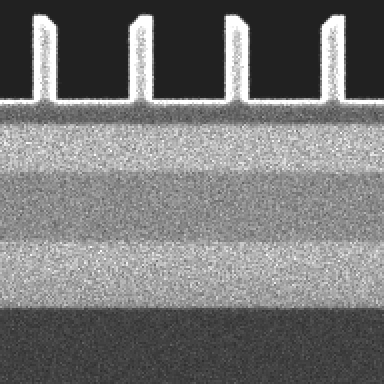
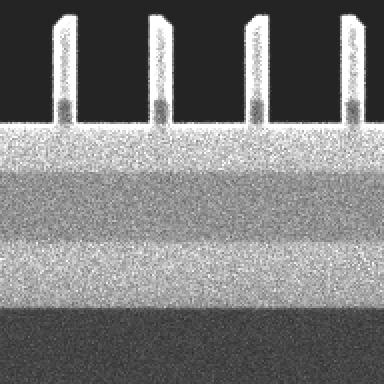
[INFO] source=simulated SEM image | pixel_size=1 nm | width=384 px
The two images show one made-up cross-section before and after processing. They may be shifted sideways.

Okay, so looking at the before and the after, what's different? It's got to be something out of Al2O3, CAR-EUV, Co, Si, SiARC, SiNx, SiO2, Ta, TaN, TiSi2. SiNx, removed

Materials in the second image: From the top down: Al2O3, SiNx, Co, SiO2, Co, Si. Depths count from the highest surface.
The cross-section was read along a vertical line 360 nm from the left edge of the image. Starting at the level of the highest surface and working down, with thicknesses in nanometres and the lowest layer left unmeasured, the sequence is empty 8, Al2O3 76, SiNx 24, Co 48, SiO2 70, Co 66, Si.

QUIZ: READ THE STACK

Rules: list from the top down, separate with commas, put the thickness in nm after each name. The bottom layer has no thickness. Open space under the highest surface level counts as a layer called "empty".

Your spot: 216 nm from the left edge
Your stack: empty 108, Co 48, SiO2 70, Co 66, Si